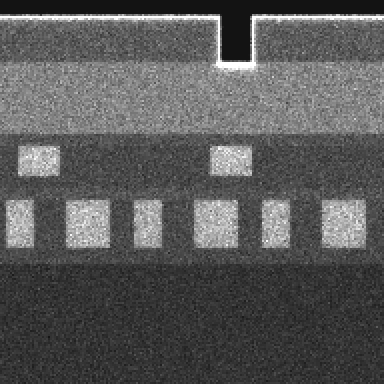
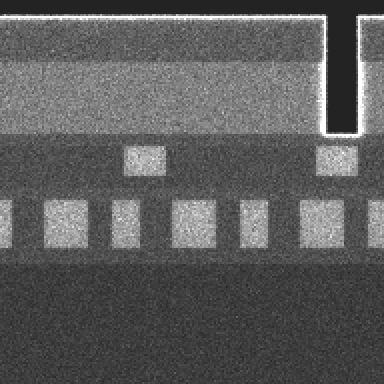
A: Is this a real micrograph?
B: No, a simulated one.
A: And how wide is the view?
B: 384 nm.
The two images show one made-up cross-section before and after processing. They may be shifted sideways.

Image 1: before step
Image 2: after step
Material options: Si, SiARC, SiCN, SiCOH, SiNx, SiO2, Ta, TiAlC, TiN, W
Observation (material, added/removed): SiO2, removed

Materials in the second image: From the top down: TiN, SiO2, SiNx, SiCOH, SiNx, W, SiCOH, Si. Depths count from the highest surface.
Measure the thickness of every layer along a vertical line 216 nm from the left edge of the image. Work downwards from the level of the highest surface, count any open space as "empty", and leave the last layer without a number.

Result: TiN 46, SiO2 72, SiNx 12, SiCOH 42, SiNx 12, SiCOH 64, Si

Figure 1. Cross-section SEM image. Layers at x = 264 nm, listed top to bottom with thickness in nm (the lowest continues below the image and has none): TiN 46, SiO2 72, SiNx 12, SiCOH 42, SiNx 12, W 48, SiCOH 16, Si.